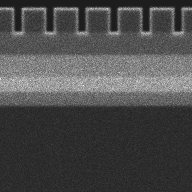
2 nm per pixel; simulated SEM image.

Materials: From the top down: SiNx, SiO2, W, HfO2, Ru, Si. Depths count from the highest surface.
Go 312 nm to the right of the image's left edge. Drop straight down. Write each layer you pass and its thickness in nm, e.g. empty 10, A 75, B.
SiNx 48, SiO2 46, W 44, HfO2 30, Ru 28, Si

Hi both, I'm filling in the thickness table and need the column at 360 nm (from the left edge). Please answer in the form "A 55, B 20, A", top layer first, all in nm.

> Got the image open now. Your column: empty 48, SiO2 46, W 44, HfO2 30, Ru 28, Si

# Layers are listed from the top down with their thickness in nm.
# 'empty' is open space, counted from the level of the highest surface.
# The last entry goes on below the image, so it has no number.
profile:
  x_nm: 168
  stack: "empty 48, SiO2 46, W 44, HfO2 30, Ru 28, Si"